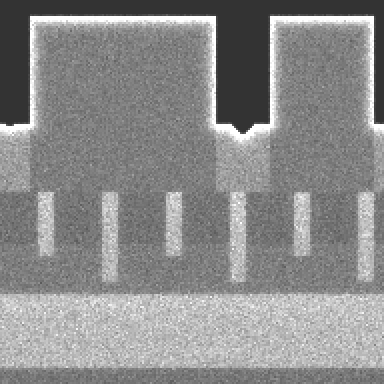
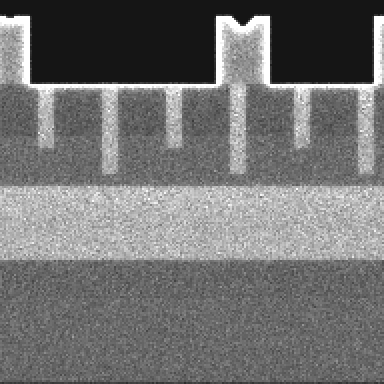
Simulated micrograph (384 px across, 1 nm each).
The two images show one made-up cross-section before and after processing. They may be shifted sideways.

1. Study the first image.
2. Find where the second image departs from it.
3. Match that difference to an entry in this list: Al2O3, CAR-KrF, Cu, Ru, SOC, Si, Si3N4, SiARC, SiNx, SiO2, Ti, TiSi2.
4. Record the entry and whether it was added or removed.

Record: SOC / removed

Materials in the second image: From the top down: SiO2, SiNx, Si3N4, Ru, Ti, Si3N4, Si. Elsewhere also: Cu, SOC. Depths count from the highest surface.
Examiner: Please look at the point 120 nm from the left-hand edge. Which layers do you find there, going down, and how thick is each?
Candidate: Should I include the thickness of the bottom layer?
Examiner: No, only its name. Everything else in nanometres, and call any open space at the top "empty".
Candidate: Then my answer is empty 68, SiNx 52, Si3N4 50, Ru 74, Ti 38, Si3N4 84, Si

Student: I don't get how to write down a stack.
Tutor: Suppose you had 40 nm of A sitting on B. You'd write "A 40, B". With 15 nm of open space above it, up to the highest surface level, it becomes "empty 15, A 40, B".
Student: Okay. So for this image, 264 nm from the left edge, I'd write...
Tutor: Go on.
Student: SiO2 68, SiNx 52, Si3N4 50, Ru 74, Ti 38, Si3N4 84, Si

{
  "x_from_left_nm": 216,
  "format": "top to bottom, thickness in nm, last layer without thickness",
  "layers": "SiO2 68, SiNx 52, Si3N4 50, Ru 74, Ti 38, Si3N4 84, Si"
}